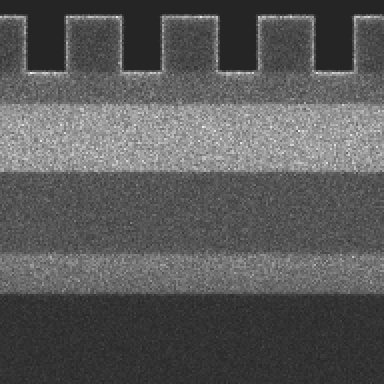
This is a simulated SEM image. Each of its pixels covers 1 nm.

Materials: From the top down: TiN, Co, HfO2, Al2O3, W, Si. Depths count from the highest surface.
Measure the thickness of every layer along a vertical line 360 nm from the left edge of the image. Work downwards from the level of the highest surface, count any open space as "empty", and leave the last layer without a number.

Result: TiN 56, Co 32, HfO2 68, Al2O3 82, W 40, Si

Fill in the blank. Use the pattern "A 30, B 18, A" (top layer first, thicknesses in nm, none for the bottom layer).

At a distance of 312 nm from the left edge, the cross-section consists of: TiN 56, Co 32, HfO2 68, Al2O3 82, W 40, Si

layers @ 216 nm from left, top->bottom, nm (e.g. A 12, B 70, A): TiN 56, Co 32, HfO2 68, Al2O3 82, W 40, Si